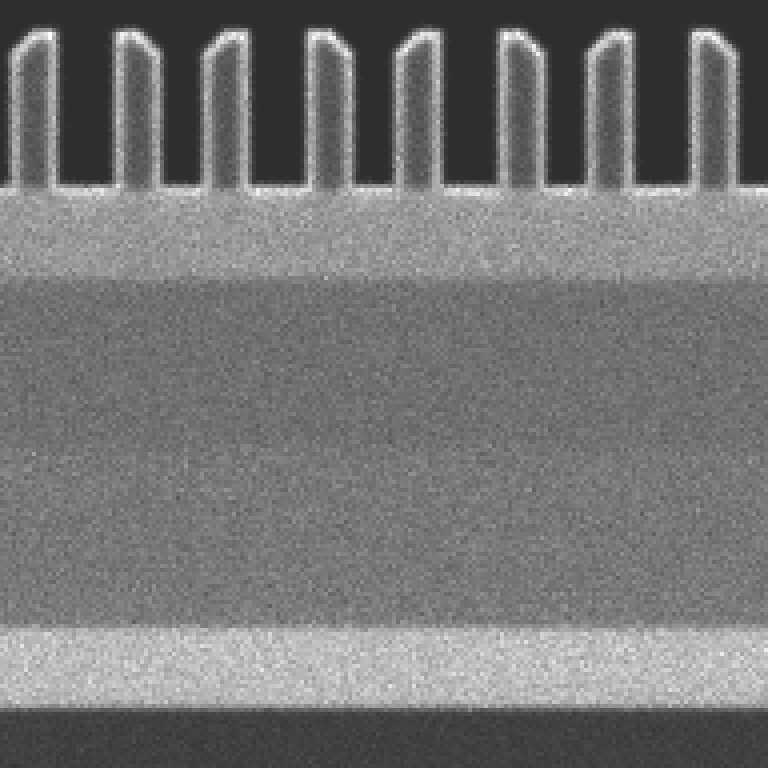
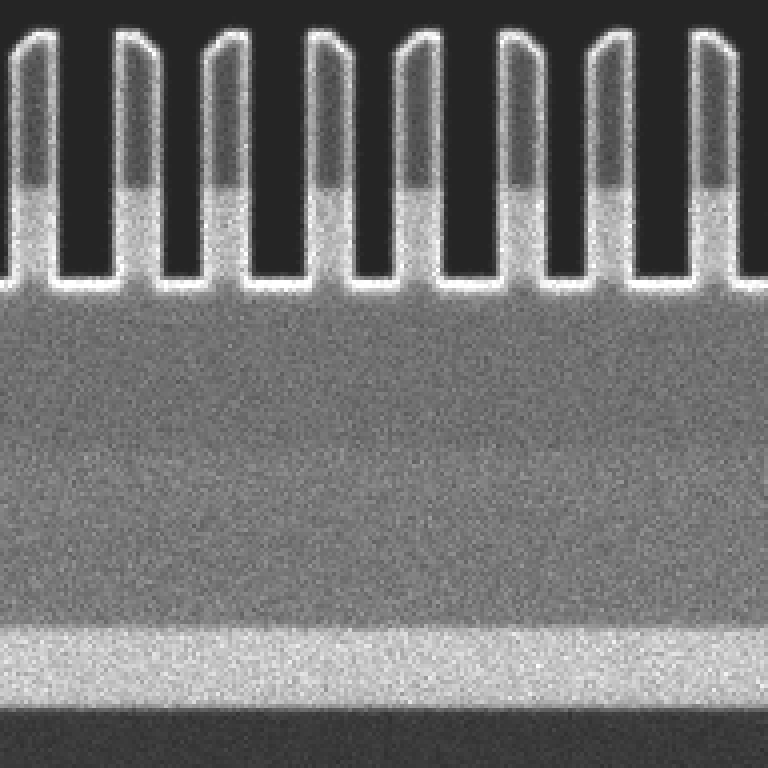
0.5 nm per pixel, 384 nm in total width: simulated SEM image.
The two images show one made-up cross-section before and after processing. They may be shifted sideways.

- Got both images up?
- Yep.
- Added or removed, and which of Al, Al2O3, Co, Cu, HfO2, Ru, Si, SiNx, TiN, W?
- removed, W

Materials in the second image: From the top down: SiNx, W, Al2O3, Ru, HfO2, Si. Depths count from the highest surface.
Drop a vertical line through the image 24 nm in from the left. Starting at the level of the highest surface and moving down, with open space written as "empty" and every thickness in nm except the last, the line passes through SiNx 78, W 46, Al2O3 84, Ru 90, HfO2 40, Si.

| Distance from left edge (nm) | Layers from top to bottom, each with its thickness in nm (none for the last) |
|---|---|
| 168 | empty 4, SiNx 74, W 46, Al2O3 84, Ru 90, HfO2 40, Si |